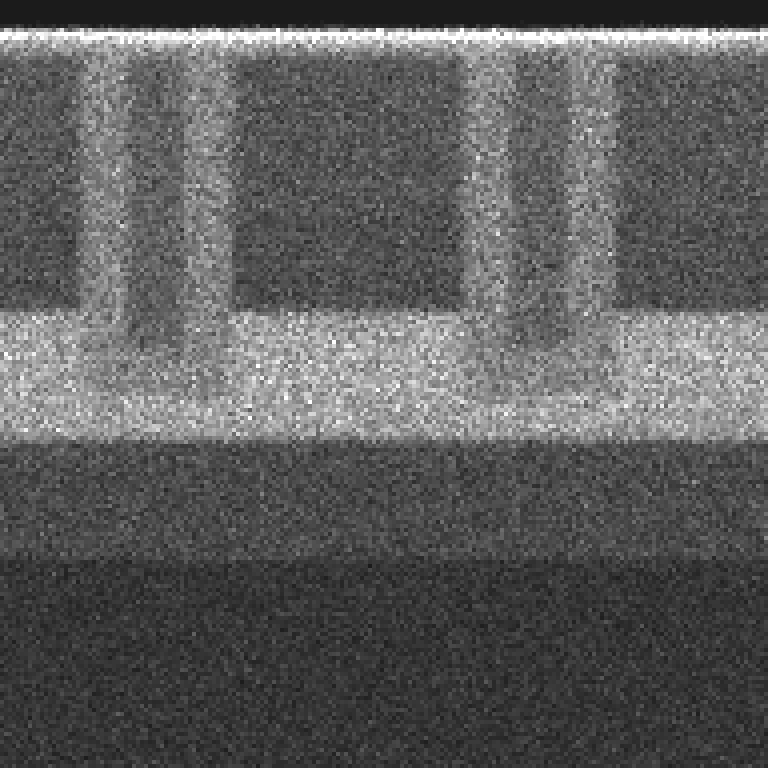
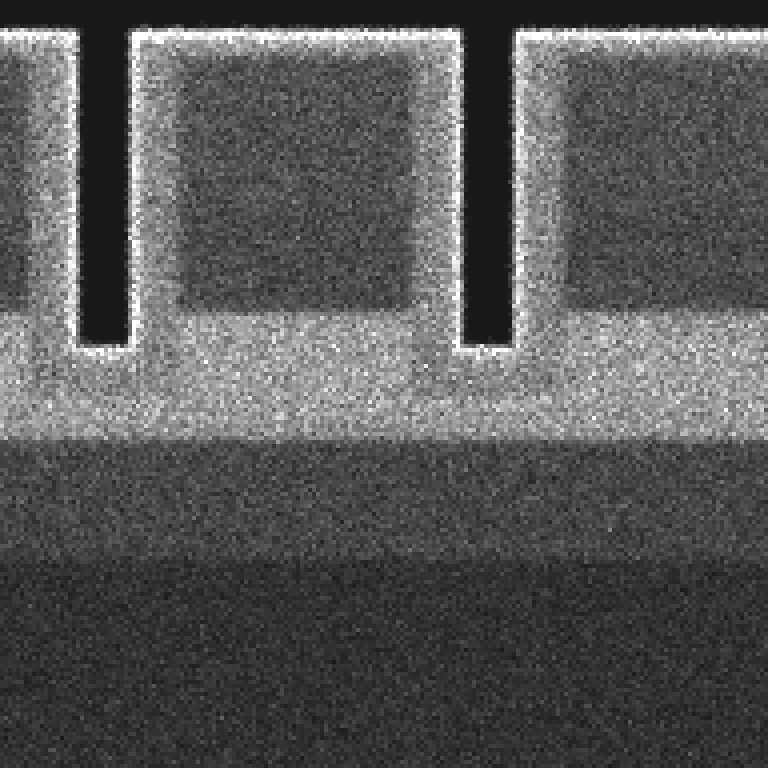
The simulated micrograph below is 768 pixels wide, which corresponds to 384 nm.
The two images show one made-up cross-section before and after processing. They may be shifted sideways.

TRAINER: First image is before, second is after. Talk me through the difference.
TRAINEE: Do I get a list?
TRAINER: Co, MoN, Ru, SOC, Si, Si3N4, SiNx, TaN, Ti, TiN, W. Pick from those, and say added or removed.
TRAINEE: removed: SOC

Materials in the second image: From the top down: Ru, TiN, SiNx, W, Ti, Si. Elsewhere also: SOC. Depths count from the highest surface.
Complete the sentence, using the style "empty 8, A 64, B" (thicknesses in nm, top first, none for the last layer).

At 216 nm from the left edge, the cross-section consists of Ru 182, W 22, Ti 60, Si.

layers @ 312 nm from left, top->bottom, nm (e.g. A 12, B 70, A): Ru 12, TiN 78, SiNx 50, W 64, Ti 60, Si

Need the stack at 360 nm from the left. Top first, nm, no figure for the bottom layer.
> Ru 12, TiN 78, SiNx 50, W 64, Ti 60, Si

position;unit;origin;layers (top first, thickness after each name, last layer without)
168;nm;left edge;Ru 12, TiN 78, SiNx 50, W 64, Ti 60, Si